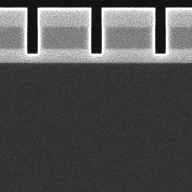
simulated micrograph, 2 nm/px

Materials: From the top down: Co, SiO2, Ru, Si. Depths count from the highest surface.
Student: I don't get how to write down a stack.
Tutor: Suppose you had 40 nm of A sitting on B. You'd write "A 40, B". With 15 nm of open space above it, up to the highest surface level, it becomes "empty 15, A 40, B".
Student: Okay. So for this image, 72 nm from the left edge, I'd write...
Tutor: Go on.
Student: empty 92, Ru 18, Si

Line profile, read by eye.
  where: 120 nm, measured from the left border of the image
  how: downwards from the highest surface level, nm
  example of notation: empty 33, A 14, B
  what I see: Co 38, SiO2 44, Ru 28, Si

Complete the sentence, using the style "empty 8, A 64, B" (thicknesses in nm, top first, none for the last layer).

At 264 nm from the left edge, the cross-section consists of Co 38, SiO2 44, Ru 28, Si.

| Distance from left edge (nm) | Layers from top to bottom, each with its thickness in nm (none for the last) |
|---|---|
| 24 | Co 38, SiO2 44, Ru 28, Si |